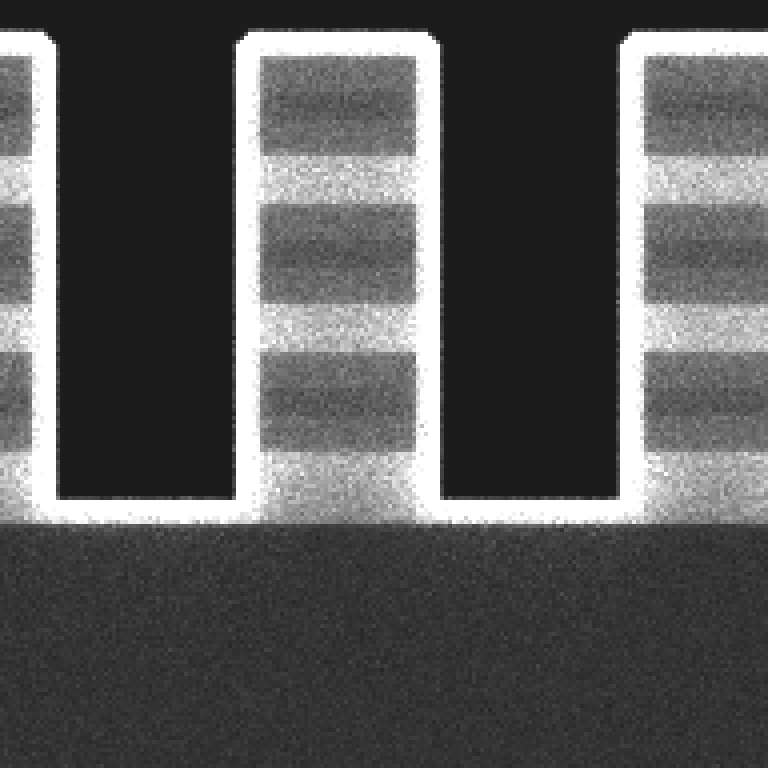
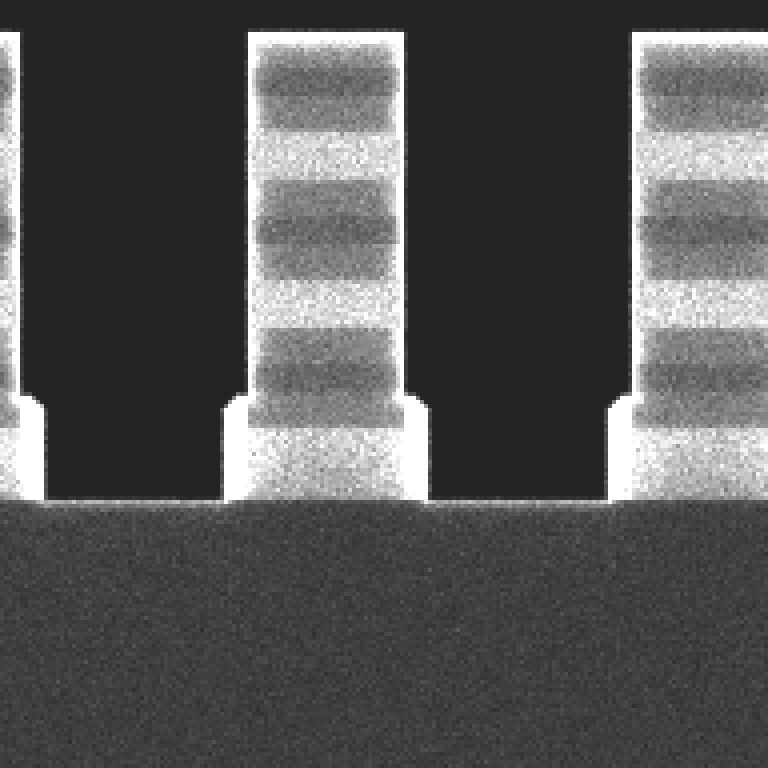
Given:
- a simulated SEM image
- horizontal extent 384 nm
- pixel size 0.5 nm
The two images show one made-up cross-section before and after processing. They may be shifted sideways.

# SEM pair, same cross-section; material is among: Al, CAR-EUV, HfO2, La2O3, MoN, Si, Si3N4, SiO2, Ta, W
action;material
removed;HfO2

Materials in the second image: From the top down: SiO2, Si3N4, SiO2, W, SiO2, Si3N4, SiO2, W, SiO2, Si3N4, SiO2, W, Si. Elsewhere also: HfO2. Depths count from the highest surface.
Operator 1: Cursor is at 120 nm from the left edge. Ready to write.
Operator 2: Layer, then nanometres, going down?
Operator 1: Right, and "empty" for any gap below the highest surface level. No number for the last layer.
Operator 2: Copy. empty 182, HfO2 52, Si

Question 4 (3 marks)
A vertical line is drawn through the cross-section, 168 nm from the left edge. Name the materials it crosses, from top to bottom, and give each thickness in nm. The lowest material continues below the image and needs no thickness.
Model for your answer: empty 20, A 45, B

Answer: SiO2 18, Si3N4 14, SiO2 18, W 24, SiO2 18, Si3N4 14, SiO2 18, W 24, SiO2 18, Si3N4 14, SiO2 18, W 36, Si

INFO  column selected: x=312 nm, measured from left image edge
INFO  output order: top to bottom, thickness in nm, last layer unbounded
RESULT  empty 182, HfO2 52, Si